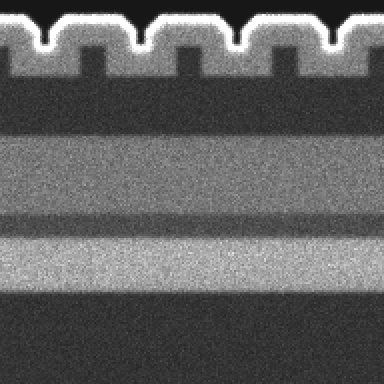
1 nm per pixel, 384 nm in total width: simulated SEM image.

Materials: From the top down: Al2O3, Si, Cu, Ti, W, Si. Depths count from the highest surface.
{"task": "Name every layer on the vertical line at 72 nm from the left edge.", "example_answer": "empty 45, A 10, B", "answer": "Al2O3 60, Si 60, Cu 78, Ti 24, W 54, Si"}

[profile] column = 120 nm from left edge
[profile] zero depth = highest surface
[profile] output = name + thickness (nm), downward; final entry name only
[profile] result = Al2O3 60, Si 60, Cu 78, Ti 24, W 54, Si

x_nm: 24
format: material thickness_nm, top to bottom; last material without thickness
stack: Al2O3 60, Si 60, Cu 78, Ti 24, W 54, Si